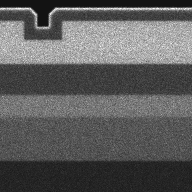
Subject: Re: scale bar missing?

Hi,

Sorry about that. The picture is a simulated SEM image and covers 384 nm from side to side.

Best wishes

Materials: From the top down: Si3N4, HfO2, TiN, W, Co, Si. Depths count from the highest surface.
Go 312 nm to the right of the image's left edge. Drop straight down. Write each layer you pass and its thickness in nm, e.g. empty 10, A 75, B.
Si3N4 26, HfO2 86, TiN 62, W 44, Co 88, Si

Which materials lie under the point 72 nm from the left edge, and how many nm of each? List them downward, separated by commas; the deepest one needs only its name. empty 12, Si3N4 52, HfO2 48, TiN 62, W 44, Co 88, Si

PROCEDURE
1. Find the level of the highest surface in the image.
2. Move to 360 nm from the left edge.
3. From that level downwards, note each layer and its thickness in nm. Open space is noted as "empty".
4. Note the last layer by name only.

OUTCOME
Si3N4 26, HfO2 86, TiN 62, W 44, Co 88, Si